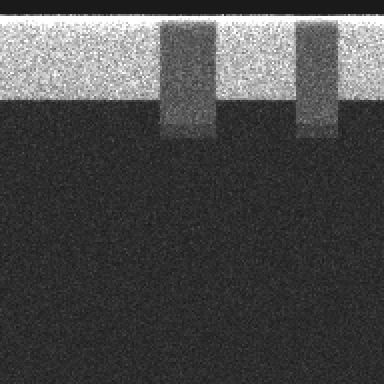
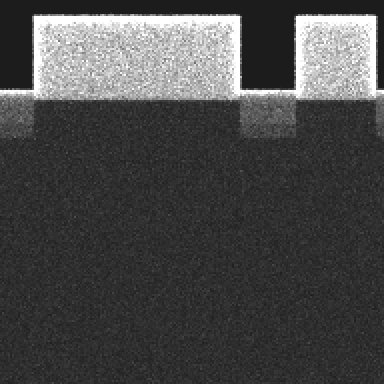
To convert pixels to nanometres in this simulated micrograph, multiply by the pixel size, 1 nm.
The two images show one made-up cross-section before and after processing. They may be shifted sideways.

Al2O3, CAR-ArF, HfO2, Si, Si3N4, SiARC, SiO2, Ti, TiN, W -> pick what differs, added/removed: SiO2 removed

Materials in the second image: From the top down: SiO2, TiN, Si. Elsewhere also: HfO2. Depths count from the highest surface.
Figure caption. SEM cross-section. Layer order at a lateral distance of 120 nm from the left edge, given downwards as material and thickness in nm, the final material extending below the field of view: HfO2 84, Si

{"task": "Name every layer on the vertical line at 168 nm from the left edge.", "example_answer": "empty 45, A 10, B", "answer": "HfO2 84, Si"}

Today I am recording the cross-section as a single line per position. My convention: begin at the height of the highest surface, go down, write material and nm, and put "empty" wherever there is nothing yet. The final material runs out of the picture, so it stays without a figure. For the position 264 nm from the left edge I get empty 74, SiO2 34, TiN 14, Si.